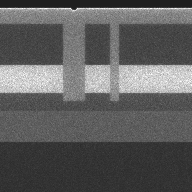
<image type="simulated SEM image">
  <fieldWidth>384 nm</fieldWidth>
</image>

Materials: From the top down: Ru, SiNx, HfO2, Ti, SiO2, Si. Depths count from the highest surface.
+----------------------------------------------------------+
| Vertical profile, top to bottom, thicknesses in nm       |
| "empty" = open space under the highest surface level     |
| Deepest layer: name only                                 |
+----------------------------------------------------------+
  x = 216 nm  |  Ru 32, SiNx 82, HfO2 56, Ti 36, SiO2 62, Si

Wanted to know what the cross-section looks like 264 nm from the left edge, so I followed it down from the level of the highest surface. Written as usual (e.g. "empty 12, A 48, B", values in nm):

Ru 32, SiNx 82, HfO2 56, Ti 36, SiO2 62, Si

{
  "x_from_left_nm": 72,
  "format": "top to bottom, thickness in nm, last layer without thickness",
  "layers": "Ru 32, SiNx 82, HfO2 56, Ti 36, SiO2 62, Si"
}